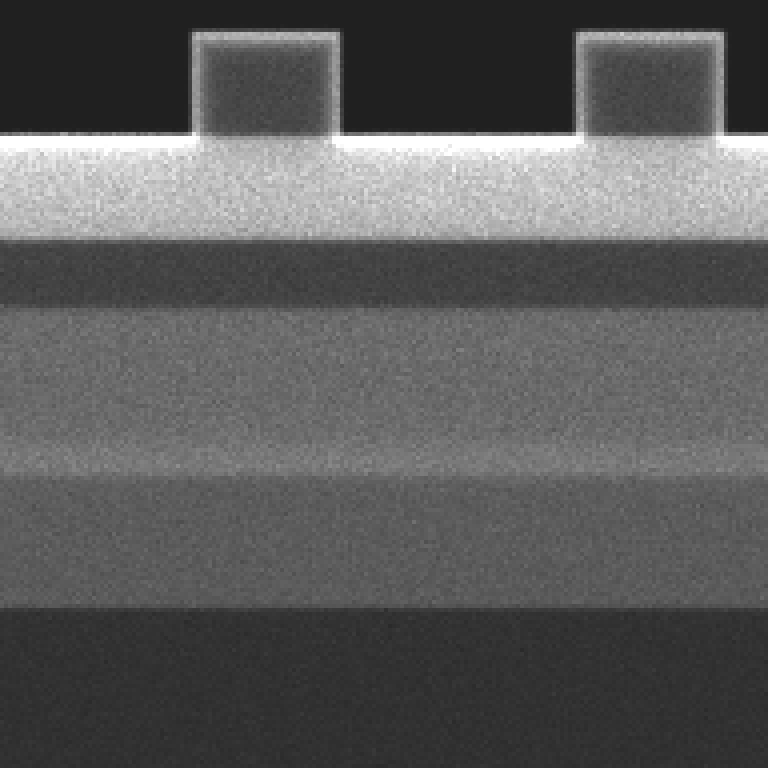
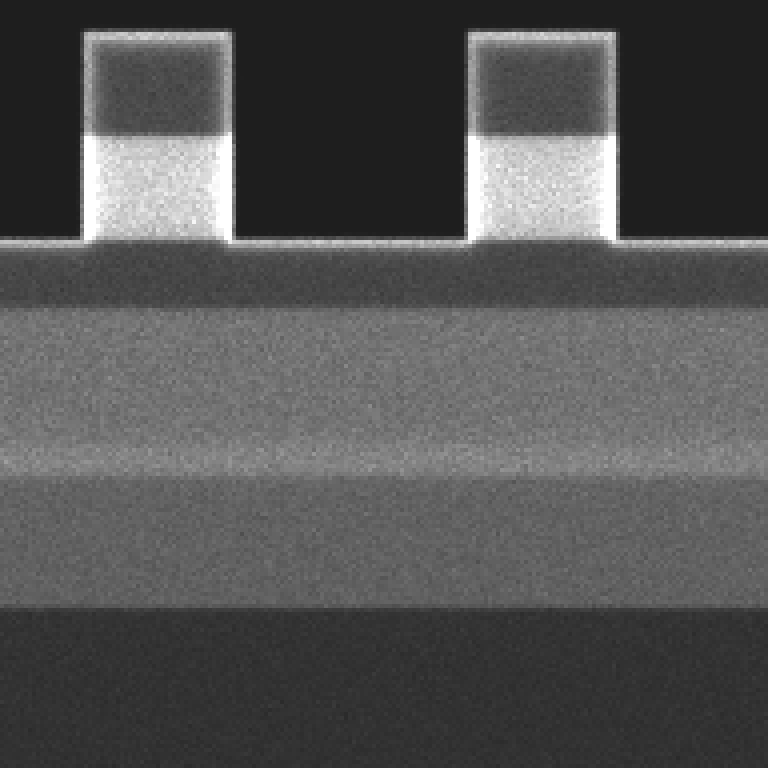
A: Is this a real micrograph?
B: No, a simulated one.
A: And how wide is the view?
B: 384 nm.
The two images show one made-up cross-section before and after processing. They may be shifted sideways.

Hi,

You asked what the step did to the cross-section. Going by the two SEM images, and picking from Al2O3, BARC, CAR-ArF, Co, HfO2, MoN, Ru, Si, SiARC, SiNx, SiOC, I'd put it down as HfO2, removed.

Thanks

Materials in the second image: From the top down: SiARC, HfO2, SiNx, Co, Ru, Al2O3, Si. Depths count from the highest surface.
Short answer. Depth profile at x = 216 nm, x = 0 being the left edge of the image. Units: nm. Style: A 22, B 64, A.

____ empty 104, SiNx 34, Co 68, Ru 16, Al2O3 66, Si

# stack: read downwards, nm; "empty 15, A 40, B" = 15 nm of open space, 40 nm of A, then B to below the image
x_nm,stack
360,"empty 104, SiNx 34, Co 68, Ru 16, Al2O3 66, Si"